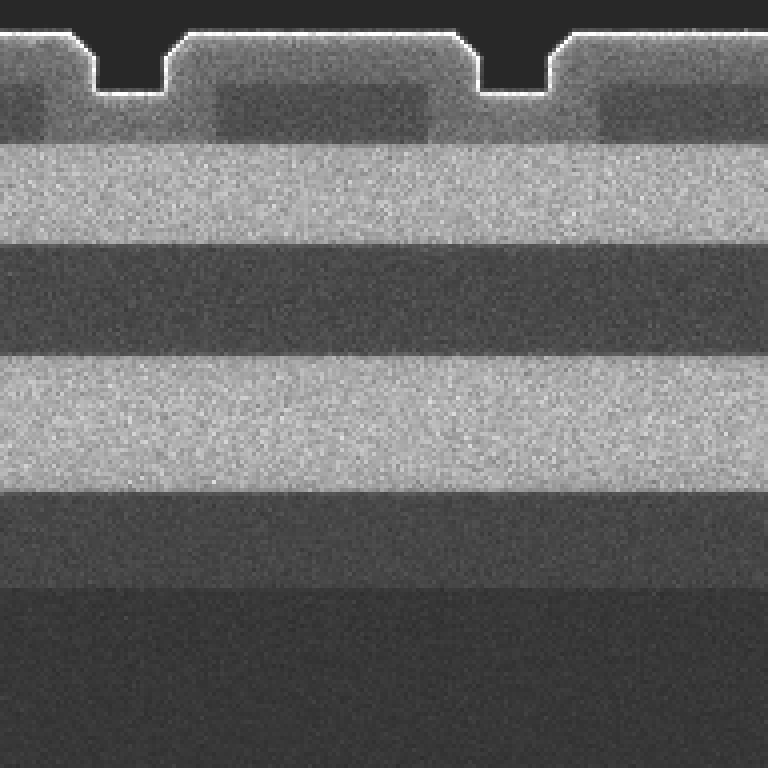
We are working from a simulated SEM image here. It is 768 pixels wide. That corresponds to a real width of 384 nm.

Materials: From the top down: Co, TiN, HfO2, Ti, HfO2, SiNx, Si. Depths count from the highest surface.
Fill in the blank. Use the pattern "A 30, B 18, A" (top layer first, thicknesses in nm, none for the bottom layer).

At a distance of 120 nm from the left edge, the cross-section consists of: Co 26, TiN 30, HfO2 50, Ti 56, HfO2 68, SiNx 48, Si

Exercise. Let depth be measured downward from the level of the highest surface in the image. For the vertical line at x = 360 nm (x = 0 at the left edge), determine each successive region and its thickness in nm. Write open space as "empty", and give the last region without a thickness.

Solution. Co 26, TiN 30, HfO2 50, Ti 56, HfO2 68, SiNx 48, Si